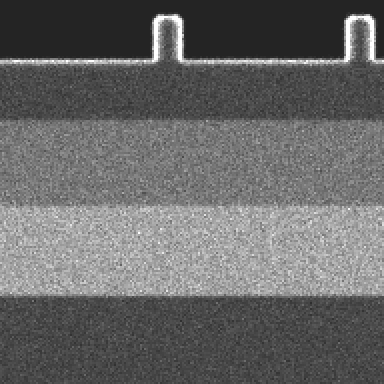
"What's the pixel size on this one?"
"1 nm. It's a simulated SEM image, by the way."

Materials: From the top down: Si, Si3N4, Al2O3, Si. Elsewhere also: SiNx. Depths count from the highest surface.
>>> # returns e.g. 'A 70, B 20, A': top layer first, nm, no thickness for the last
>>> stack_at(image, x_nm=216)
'empty 44, Si 60, Si3N4 86, Al2O3 90, Si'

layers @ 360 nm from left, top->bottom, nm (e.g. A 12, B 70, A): Si 104, Si3N4 86, Al2O3 90, Si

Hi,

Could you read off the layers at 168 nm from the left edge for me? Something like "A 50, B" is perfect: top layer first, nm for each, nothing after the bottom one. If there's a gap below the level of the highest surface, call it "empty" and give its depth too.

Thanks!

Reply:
Si 104, Si3N4 86, Al2O3 90, Si